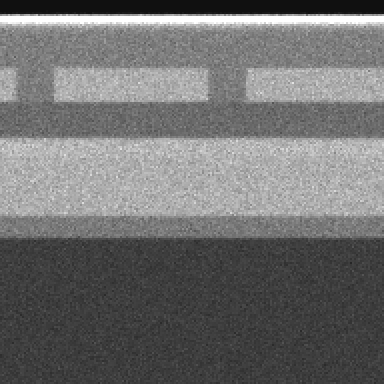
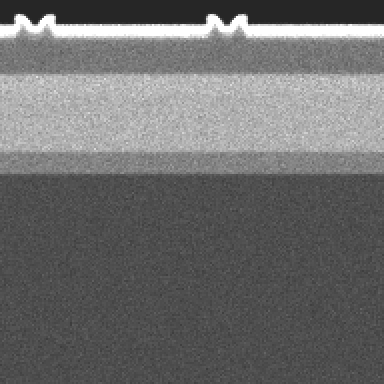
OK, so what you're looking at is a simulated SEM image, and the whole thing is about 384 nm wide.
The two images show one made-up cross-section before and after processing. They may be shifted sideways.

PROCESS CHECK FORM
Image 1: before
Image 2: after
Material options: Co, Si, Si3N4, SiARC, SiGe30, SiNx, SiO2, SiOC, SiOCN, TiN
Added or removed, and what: removed, SiARC and SiO2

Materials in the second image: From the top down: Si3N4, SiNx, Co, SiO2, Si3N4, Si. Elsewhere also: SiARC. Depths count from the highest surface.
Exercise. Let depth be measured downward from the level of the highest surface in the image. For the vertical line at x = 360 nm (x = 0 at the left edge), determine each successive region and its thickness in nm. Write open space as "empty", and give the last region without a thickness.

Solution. empty 10, SiO2 12, SiNx 36, Co 18, SiO2 60, Si3N4 22, Si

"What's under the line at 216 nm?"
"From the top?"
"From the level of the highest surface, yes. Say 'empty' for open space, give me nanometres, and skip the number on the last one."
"empty 2, Si3N4 20, SiNx 36, Co 18, SiO2 60, Si3N4 22, Si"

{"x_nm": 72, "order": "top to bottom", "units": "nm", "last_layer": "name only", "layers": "empty 10, SiO2 12, SiNx 36, Co 18, SiO2 60, Si3N4 22, Si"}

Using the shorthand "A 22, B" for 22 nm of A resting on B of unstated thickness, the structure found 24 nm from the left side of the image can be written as empty 2, Si3N4 20, SiNx 36, Co 18, SiO2 60, Si3N4 22, Si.